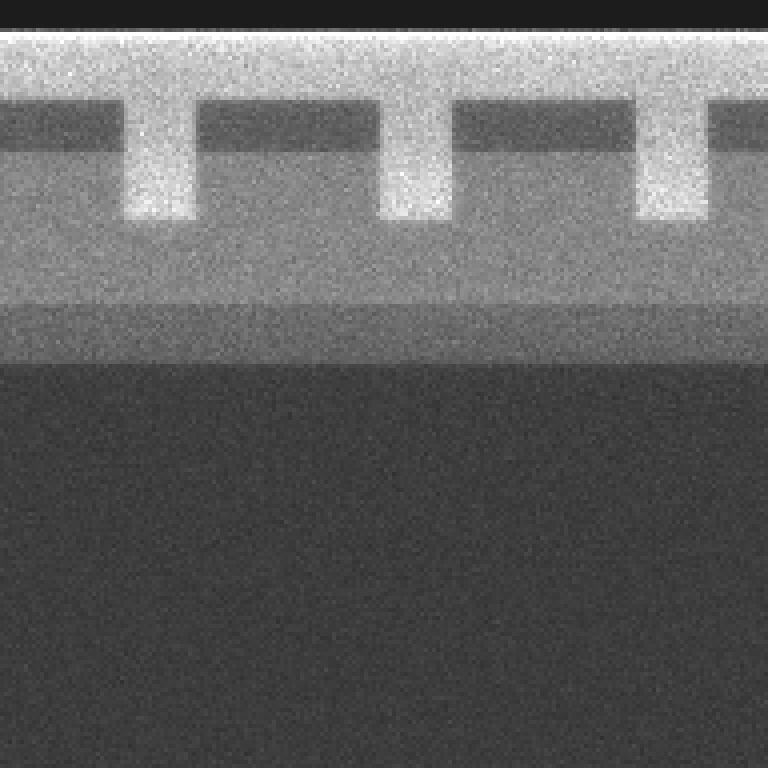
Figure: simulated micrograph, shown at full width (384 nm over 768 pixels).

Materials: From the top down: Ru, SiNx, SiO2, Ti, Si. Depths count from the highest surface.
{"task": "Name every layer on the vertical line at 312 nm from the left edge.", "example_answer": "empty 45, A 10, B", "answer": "Ru 34, SiNx 26, SiO2 76, Ti 30, Si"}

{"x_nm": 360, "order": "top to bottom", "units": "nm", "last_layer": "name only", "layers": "Ru 34, SiNx 26, SiO2 76, Ti 30, Si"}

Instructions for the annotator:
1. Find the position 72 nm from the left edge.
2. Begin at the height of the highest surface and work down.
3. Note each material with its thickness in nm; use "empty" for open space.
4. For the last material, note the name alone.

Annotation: Ru 94, SiO2 42, Ti 30, Si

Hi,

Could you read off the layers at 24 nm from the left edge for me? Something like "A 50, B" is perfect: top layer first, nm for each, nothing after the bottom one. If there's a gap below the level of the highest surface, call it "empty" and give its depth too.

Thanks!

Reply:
Ru 34, SiNx 26, SiO2 76, Ti 30, Si